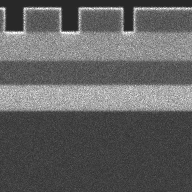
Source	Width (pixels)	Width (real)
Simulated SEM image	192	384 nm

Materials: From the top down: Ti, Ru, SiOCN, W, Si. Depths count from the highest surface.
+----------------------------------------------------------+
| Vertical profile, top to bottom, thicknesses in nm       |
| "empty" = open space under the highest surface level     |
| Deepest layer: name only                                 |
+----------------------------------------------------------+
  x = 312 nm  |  Ti 48, Ru 58, SiOCN 48, W 52, Si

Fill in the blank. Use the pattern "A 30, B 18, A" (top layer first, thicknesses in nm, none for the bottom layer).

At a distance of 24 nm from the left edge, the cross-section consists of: empty 48, Ru 58, SiOCN 48, W 52, Si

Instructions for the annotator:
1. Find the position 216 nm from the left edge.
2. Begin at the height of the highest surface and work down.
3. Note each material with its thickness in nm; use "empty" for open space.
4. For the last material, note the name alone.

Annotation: Ti 48, Ru 58, SiOCN 48, W 52, Si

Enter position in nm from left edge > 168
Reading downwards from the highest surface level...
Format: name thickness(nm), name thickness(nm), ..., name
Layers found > Ti 48, Ru 58, SiOCN 48, W 52, Si